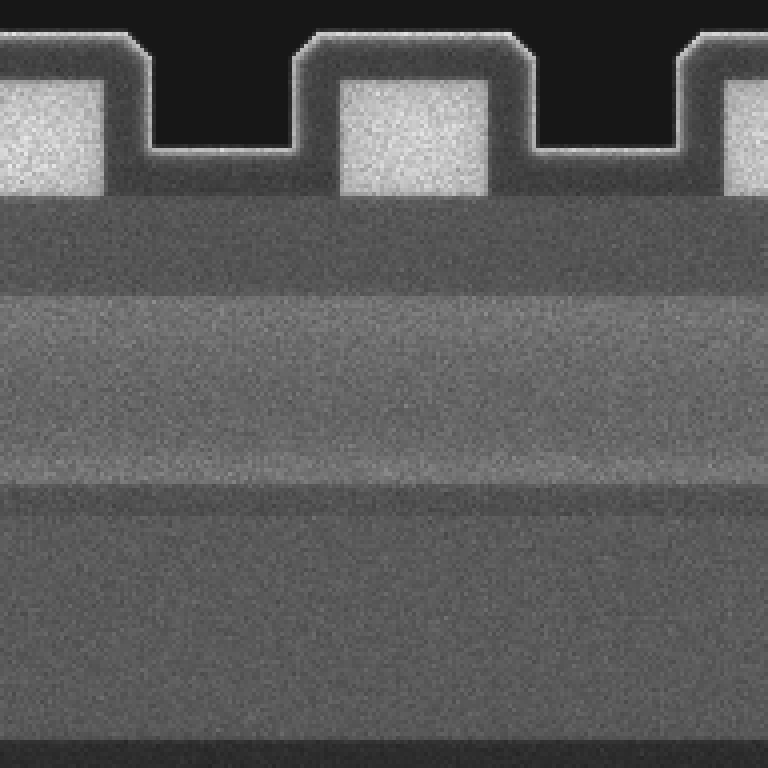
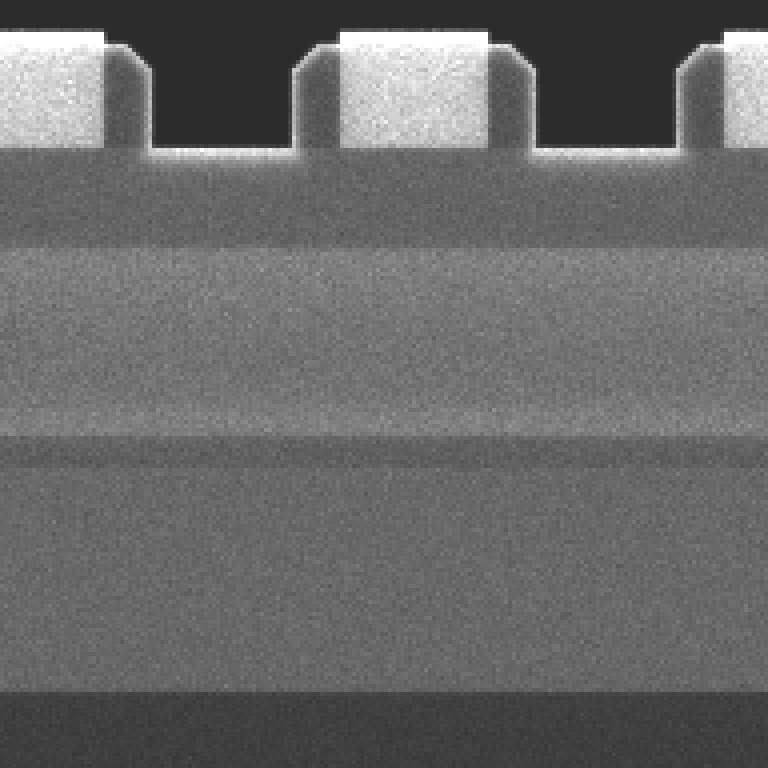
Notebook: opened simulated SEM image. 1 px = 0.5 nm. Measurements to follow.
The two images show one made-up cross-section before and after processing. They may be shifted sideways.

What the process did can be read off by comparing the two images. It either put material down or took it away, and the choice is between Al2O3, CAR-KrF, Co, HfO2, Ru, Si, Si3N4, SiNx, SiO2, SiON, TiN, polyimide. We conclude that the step removed SiNx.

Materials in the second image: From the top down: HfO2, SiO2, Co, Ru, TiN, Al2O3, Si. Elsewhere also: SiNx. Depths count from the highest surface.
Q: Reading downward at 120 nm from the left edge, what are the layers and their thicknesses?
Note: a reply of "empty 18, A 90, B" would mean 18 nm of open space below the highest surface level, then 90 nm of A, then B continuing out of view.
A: empty 58, SiO2 50, Co 80, Ru 14, TiN 16, Al2O3 112, Si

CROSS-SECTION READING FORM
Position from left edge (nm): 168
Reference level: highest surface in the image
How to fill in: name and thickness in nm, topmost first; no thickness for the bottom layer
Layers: empty 6, SiNx 52, SiO2 50, Co 80, Ru 14, TiN 16, Al2O3 112, Si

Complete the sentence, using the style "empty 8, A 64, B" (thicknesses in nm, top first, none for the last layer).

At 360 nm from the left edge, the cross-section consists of empty 6, SiNx 52, SiO2 50, Co 80, Ru 14, TiN 16, Al2O3 112, Si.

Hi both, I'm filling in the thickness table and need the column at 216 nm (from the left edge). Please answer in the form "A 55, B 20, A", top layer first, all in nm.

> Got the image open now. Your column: HfO2 58, SiO2 50, Co 80, Ru 14, TiN 16, Al2O3 112, Si